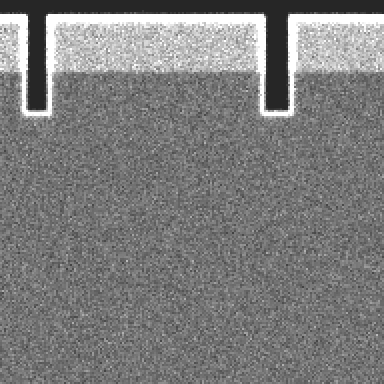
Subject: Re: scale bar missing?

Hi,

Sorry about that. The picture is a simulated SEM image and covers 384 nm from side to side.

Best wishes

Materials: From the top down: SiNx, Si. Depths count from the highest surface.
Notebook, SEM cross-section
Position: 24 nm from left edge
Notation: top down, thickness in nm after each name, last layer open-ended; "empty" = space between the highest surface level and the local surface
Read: SiNx 56, Si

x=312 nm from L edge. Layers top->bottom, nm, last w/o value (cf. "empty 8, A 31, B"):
SiNx 56, Si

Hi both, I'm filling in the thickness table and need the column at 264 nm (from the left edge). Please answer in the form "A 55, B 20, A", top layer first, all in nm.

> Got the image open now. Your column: empty 96, Si